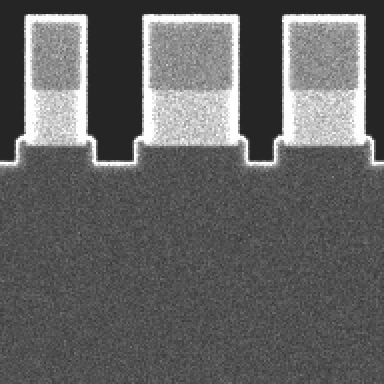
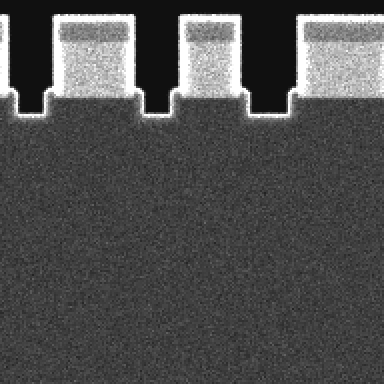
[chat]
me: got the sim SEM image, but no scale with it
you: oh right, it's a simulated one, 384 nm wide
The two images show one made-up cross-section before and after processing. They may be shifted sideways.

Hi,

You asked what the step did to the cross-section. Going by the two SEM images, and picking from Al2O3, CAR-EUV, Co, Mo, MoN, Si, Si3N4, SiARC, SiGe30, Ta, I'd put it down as Si3N4, removed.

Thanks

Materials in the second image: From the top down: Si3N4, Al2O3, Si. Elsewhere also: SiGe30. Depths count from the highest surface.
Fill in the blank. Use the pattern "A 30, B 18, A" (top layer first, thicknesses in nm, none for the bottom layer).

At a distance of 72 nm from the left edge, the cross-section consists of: Si3N4 26, Al2O3 56, Si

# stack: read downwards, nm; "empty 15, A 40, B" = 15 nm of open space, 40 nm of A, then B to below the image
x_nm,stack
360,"Si3N4 26, Al2O3 56, Si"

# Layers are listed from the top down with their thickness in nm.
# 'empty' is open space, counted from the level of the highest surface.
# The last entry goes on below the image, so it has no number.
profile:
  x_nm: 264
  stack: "empty 98, SiGe30 10, Si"